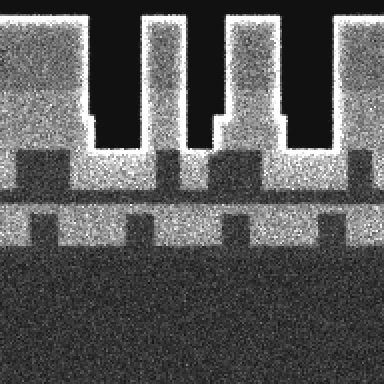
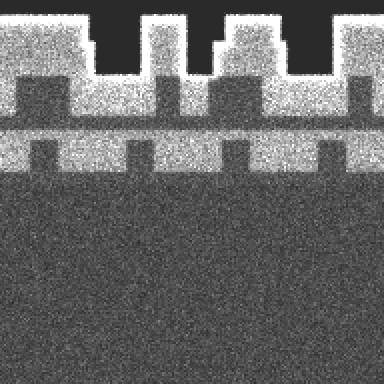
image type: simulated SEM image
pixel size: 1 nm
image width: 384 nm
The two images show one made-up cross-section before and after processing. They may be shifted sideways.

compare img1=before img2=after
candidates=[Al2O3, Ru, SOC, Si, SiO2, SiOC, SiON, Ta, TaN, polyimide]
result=removed:SOC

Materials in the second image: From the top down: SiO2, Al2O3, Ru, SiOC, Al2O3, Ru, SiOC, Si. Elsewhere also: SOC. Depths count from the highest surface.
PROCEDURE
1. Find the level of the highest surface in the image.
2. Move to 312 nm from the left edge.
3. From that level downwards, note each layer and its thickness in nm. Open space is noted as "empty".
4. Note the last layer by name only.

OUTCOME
empty 60, Ru 40, SiOC 14, Al2O3 10, Ru 32, SiOC 12, Si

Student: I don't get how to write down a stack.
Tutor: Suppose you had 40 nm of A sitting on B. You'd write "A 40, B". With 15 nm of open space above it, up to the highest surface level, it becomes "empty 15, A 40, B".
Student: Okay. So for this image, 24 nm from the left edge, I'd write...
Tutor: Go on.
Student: SiO2 48, Al2O3 12, SiOC 54, Al2O3 10, Ru 32, SiOC 12, Si